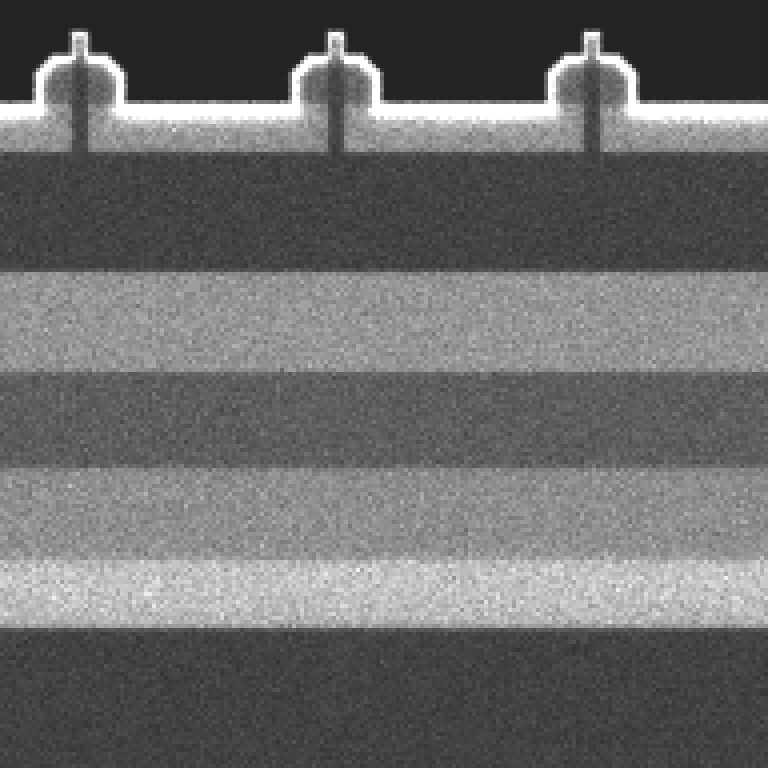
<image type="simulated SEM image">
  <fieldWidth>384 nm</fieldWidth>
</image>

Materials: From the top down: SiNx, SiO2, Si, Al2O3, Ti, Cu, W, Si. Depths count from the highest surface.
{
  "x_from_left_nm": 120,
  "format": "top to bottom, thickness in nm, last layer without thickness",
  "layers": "empty 36, SiO2 24, Si 60, Al2O3 50, Ti 48, Cu 46, W 34, Si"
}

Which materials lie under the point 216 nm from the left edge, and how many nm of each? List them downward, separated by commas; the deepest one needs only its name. empty 36, SiO2 24, Si 60, Al2O3 50, Ti 48, Cu 46, W 34, Si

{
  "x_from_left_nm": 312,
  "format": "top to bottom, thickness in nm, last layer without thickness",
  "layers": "empty 16, SiNx 20, SiO2 24, Si 60, Al2O3 50, Ti 48, Cu 46, W 34, Si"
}